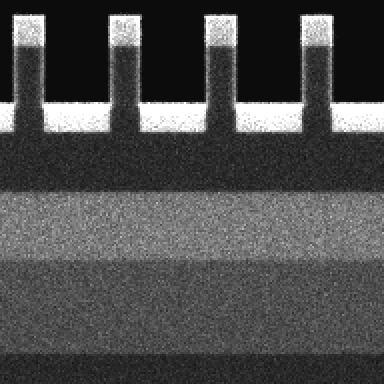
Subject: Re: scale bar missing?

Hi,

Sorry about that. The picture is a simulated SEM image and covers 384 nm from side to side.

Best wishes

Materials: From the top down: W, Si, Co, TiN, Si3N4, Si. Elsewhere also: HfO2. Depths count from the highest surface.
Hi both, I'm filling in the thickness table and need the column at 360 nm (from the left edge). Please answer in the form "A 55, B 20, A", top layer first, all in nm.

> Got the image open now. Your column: empty 88, HfO2 28, Si 60, Co 68, TiN 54, Si3N4 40, Si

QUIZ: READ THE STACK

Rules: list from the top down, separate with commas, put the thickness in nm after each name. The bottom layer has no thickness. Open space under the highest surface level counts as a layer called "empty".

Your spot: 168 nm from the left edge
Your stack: empty 88, HfO2 28, Si 60, Co 68, TiN 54, Si3N4 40, Si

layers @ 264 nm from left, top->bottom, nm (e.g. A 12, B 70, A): empty 88, HfO2 28, Si 60, Co 68, TiN 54, Si3N4 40, Si